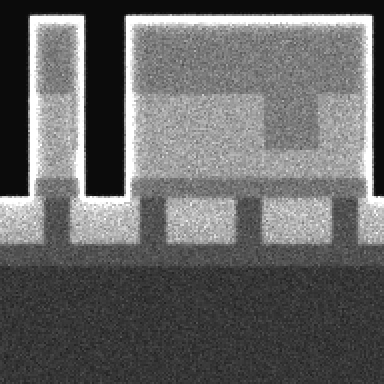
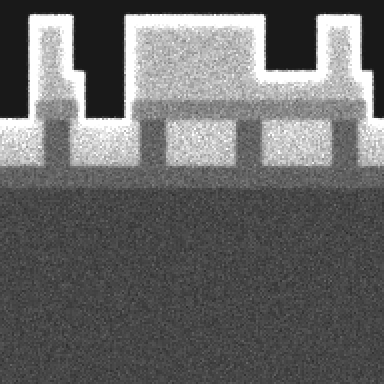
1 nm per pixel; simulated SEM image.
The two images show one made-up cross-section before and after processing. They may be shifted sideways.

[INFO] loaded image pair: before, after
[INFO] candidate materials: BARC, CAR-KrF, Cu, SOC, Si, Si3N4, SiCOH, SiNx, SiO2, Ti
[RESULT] removed SOC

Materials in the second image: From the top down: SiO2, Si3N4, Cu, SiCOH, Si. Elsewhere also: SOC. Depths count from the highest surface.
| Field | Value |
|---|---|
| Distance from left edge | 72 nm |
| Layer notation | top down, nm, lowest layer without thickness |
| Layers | empty 56, SiO2 28, Si3N4 20, Cu 46, SiCOH 22, Si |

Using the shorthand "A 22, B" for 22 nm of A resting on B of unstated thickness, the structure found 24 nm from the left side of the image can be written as empty 104, Cu 46, SiCOH 22, Si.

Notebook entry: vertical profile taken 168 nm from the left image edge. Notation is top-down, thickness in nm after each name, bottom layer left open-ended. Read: SiO2 84, Si3N4 20, Cu 46, SiCOH 22, Si